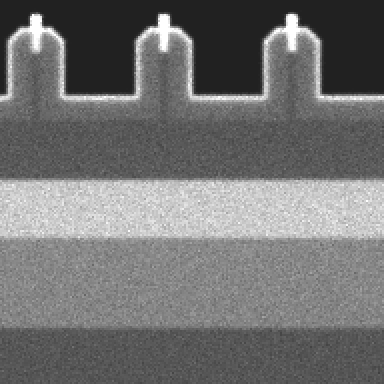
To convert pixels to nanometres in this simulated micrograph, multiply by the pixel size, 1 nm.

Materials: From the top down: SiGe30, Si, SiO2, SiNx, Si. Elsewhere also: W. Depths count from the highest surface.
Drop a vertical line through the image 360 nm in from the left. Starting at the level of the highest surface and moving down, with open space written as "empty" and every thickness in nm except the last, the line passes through empty 80, SiGe30 24, Si 60, SiO2 58, SiNx 90, Si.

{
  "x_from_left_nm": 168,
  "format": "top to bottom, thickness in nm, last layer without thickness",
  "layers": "empty 12, SiGe30 92, Si 60, SiO2 58, SiNx 90, Si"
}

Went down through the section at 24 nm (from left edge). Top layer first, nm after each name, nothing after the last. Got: empty 12, SiGe30 92, Si 60, SiO2 58, SiNx 90, Si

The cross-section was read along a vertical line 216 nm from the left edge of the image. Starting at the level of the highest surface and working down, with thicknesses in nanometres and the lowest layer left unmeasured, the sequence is empty 80, SiGe30 24, Si 60, SiO2 58, SiNx 90, Si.